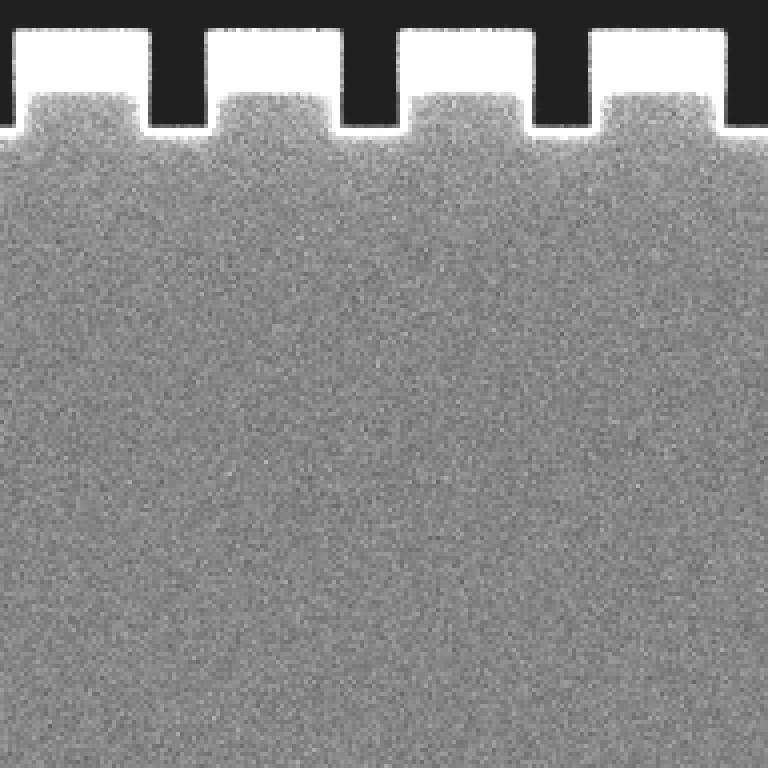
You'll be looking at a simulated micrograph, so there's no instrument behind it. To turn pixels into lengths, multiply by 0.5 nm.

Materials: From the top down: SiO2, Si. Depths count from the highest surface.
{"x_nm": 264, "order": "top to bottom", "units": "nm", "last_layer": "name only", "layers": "SiO2 30, Si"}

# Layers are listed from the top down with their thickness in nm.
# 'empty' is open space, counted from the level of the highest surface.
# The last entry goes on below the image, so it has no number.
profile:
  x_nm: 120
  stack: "SiO2 30, Si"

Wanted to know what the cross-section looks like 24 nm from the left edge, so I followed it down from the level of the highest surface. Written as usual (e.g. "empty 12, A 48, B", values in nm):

SiO2 30, Si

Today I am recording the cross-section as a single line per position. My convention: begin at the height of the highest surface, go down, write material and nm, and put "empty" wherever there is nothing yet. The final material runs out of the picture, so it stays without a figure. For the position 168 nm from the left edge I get SiO2 30, Si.